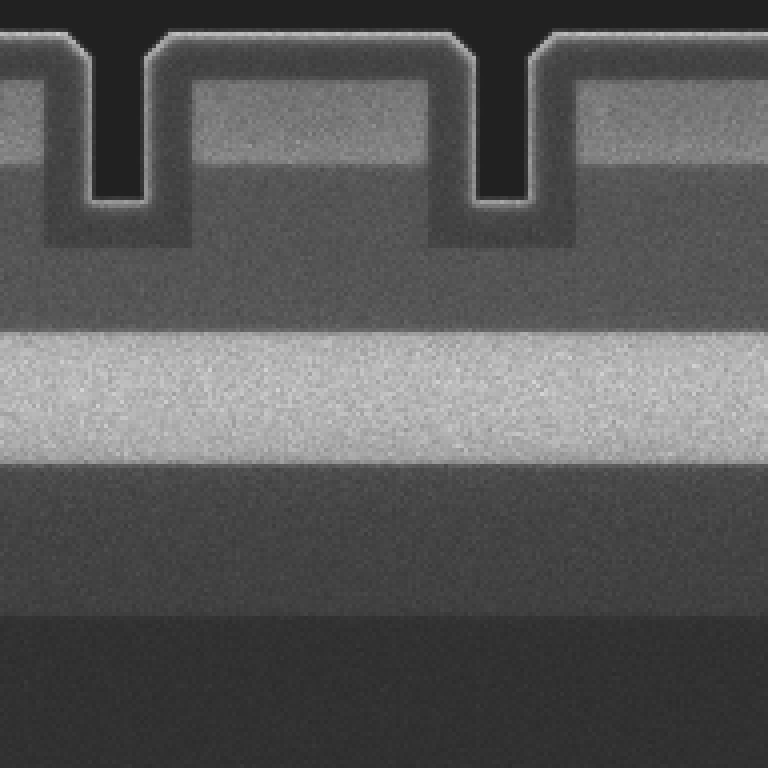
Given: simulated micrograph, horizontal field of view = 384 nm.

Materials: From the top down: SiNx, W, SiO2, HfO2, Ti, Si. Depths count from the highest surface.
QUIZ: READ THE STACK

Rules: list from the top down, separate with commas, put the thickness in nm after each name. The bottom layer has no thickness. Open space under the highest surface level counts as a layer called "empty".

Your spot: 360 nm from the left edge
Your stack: SiNx 24, W 42, SiO2 84, HfO2 66, Ti 76, Si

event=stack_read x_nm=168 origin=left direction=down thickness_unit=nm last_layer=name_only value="SiNx 24, W 42, SiO2 84, HfO2 66, Ti 76, Si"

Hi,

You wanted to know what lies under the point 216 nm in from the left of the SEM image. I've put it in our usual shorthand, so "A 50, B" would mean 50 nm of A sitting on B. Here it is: SiNx 108, SiO2 42, HfO2 66, Ti 76, Si